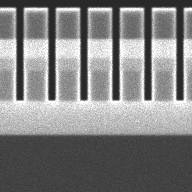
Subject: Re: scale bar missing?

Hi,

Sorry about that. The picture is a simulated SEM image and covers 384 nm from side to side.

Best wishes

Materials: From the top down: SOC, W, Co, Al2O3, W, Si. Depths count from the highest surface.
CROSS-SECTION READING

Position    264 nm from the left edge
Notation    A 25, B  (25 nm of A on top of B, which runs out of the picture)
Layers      SOC 62, W 38, Co 26, Al2O3 60, W 68, Si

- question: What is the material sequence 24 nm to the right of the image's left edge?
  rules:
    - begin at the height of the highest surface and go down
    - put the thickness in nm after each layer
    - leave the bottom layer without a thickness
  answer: SOC 62, W 38, Co 26, Al2O3 60, W 68, Si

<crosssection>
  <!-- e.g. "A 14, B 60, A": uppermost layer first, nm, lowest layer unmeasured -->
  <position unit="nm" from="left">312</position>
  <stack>SOC 62, W 38, Co 26, Al2O3 60, W 68, Si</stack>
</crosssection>